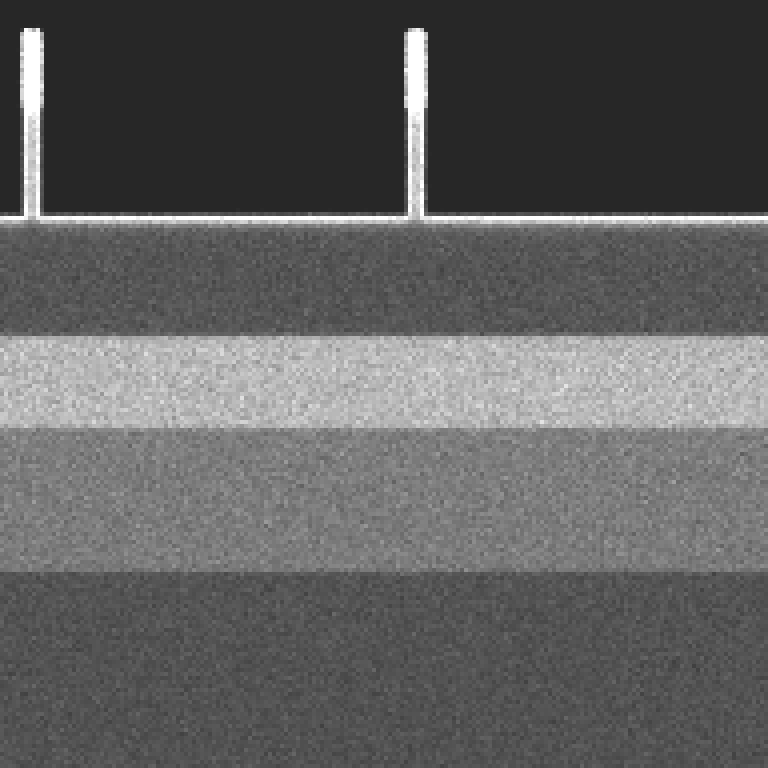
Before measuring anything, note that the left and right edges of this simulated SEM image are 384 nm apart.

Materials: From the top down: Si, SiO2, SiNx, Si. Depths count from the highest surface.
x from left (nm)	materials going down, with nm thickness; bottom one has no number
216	empty 92, Si 60, SiO2 46, SiNx 72, Si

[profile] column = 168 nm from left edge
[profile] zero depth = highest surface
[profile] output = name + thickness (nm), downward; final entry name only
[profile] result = empty 92, Si 60, SiO2 46, SiNx 72, Si